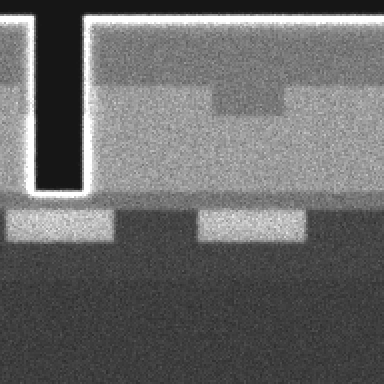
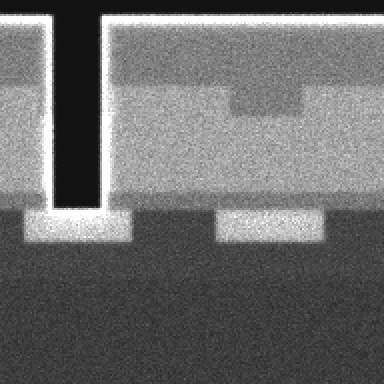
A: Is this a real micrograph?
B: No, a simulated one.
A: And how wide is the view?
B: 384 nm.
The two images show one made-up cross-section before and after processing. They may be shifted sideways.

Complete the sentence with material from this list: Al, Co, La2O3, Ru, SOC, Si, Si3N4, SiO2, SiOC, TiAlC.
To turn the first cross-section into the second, Si3N4 must be removed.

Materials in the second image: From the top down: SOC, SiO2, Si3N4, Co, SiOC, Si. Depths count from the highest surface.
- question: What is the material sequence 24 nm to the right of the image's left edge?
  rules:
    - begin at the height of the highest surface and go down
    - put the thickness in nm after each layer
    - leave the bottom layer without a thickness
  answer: SOC 70, SiO2 106, Si3N4 18, Co 32, SiOC 38, Si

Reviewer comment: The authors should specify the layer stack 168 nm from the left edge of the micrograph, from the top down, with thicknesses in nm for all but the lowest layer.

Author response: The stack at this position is SOC 70, SiO2 106, Si3N4 18, SiOC 70, Si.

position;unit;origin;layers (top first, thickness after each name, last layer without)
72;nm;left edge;empty 194, Co 32, SiOC 38, Si